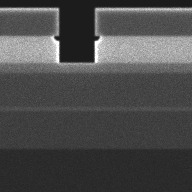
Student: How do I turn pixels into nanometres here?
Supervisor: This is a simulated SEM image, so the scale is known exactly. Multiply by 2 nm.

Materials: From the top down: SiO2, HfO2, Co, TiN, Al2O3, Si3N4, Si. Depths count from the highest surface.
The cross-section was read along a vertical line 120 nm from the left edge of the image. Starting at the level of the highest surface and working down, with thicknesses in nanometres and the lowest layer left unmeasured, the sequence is empty 110, Co 20, TiN 68, Al2O3 8, Si3N4 76, Si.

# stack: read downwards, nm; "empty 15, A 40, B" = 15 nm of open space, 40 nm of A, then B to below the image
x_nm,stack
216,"SiO2 56, HfO2 54, Co 20, TiN 68, Al2O3 8, Si3N4 76, Si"